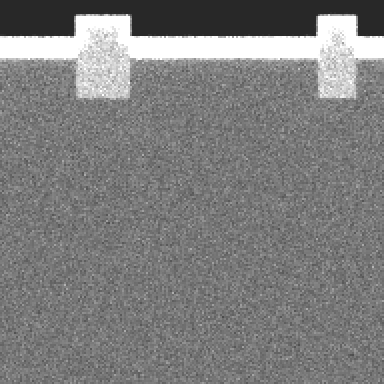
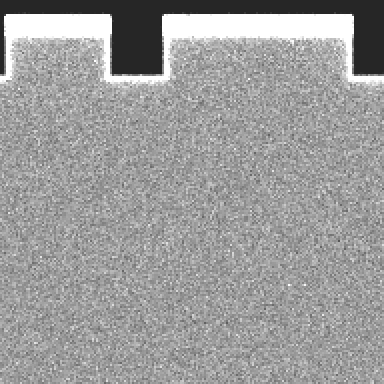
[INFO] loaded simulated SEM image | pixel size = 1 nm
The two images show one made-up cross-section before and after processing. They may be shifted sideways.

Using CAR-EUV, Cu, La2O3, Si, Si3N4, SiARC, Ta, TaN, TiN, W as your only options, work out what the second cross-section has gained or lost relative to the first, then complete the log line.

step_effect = removed SiARC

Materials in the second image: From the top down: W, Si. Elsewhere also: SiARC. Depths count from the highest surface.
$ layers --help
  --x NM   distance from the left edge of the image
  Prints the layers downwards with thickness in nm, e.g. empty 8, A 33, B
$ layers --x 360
empty 60, Si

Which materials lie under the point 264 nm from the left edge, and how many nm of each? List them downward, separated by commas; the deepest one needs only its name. W 20, Si